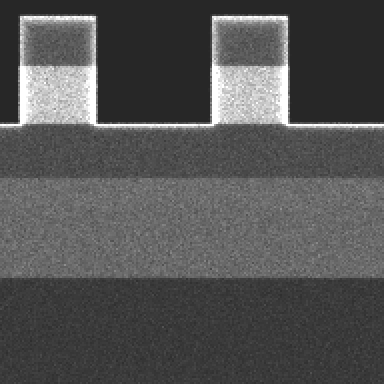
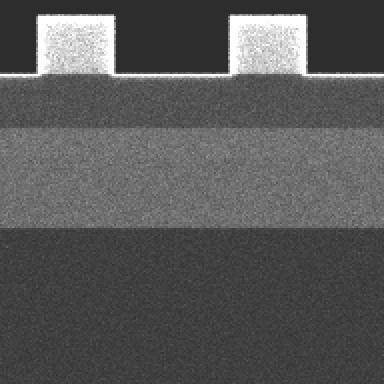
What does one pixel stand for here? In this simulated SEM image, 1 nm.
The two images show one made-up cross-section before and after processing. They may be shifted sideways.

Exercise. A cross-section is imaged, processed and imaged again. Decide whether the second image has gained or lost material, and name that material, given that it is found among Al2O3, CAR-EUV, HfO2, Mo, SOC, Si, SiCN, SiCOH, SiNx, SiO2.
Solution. removed: SOC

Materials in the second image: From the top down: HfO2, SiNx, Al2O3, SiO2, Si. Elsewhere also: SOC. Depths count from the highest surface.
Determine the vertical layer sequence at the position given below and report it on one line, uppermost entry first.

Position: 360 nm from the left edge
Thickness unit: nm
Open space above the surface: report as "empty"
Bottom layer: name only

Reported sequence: empty 58, SiNx 54, Al2O3 30, SiO2 70, Si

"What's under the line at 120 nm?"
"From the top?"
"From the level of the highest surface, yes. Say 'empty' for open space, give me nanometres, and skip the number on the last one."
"empty 58, SiNx 54, Al2O3 30, SiO2 70, Si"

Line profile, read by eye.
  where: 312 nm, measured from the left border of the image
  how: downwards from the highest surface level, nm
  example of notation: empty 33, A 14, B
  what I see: empty 58, SiNx 54, Al2O3 30, SiO2 70, Si